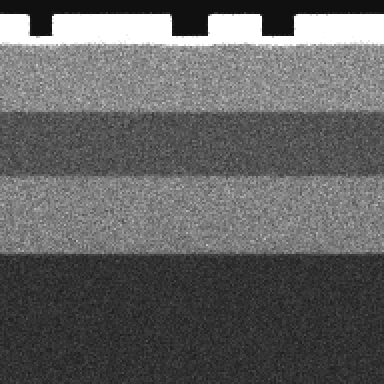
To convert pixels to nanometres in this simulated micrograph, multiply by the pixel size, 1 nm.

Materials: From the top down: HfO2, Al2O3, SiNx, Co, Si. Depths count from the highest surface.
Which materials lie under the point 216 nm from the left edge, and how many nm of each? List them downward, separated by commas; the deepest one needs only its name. HfO2 28, Al2O3 68, SiNx 64, Co 78, Si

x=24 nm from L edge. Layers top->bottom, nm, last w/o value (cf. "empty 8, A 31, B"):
HfO2 28, Al2O3 68, SiNx 64, Co 78, Si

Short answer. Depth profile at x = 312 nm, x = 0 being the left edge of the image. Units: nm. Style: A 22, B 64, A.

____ HfO2 28, Al2O3 68, SiNx 64, Co 78, Si